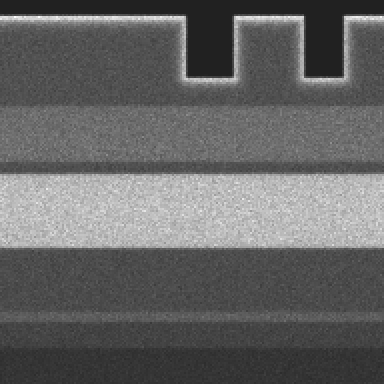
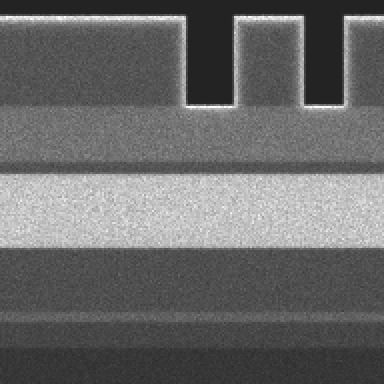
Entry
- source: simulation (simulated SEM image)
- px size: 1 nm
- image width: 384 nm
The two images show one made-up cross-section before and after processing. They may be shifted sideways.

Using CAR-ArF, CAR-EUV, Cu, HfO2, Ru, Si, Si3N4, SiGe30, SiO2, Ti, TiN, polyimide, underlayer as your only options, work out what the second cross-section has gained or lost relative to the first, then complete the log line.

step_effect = removed underlayer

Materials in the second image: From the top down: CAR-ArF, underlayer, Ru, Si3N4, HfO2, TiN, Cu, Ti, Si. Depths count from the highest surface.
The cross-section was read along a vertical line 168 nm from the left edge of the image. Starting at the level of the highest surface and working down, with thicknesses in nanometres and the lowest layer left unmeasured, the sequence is CAR-ArF 62, underlayer 28, Ru 56, Si3N4 12, HfO2 74, TiN 64, Cu 10, Ti 26, Si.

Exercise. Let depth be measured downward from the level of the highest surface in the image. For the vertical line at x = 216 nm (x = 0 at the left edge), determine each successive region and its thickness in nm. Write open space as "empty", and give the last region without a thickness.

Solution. empty 90, Ru 56, Si3N4 12, HfO2 74, TiN 64, Cu 10, Ti 26, Si